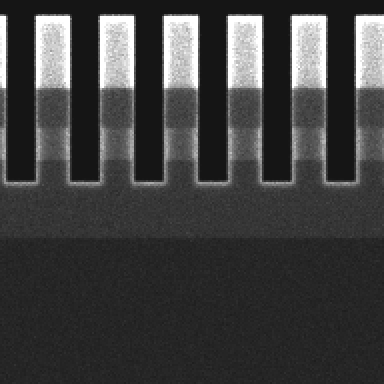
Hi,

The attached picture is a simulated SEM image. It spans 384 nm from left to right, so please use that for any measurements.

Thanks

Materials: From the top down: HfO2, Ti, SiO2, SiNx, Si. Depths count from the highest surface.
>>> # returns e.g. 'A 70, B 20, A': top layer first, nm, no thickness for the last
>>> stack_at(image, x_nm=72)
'empty 166, SiNx 56, Si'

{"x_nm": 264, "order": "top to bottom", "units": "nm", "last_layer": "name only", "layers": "empty 166, SiNx 56, Si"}